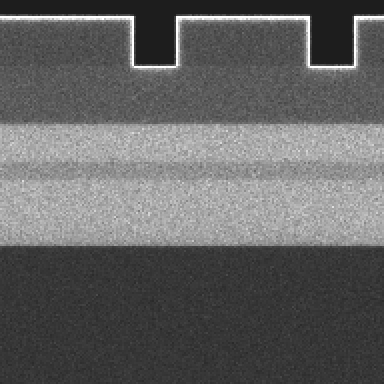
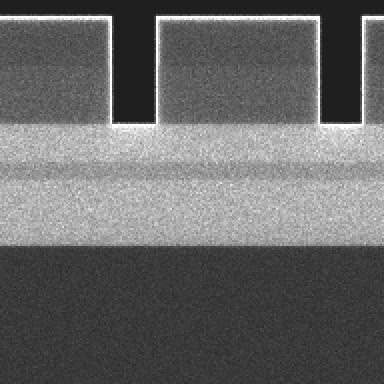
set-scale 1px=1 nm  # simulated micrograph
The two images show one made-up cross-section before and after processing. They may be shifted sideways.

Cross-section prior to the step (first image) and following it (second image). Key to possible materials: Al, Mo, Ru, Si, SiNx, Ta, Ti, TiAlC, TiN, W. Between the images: TiN was removed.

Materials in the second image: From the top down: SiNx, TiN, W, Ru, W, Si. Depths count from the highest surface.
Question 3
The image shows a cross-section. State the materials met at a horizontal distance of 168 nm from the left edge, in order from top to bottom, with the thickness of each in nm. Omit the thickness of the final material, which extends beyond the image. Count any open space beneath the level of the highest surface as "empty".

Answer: SiNx 50, TiN 58, W 38, Ru 18, W 66, Si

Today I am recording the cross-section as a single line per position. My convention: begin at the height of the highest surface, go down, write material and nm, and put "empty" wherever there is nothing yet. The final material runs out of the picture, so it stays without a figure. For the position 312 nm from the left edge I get SiNx 50, TiN 58, W 38, Ru 18, W 66, Si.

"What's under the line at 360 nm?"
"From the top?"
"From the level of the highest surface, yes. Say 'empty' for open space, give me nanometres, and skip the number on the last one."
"empty 108, W 38, Ru 18, W 66, Si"